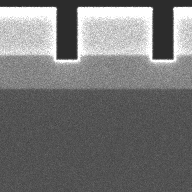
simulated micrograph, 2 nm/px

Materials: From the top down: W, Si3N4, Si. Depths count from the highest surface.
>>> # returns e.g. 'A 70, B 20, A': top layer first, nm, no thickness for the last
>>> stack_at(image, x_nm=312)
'empty 104, Si3N4 58, Si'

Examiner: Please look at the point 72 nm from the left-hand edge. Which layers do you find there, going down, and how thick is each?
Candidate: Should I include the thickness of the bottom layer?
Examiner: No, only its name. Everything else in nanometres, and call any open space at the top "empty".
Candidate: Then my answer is W 94, Si3N4 68, Si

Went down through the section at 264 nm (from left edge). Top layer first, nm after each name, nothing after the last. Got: W 94, Si3N4 68, Si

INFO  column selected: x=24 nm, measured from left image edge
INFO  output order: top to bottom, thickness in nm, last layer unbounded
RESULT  W 94, Si3N4 68, Si